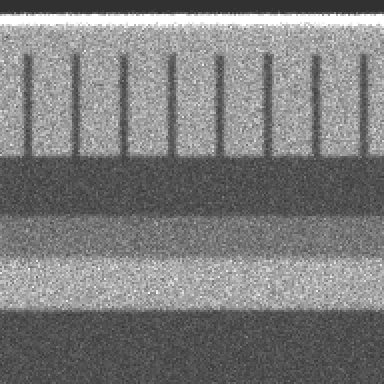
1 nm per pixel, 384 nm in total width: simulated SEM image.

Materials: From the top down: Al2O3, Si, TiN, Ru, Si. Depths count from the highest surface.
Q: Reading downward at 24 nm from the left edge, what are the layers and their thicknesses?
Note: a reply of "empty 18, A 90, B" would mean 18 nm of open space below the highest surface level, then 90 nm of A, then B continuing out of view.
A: Al2O3 38, Si 162, TiN 42, Ru 52, Si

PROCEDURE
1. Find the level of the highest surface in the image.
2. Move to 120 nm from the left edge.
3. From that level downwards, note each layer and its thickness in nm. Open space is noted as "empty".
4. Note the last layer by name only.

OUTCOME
Al2O3 38, Si 162, TiN 42, Ru 52, Si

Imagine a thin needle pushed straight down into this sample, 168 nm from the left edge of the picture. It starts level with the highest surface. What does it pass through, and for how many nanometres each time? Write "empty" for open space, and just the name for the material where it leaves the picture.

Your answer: Al2O3 38, Si 162, TiN 42, Ru 52, Si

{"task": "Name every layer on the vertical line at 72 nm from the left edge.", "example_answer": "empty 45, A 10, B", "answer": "Al2O3 38, Si 162, TiN 42, Ru 52, Si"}